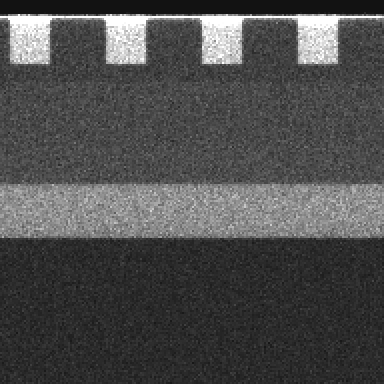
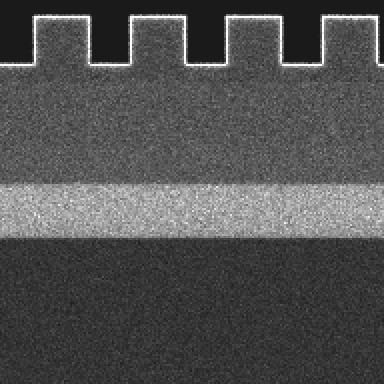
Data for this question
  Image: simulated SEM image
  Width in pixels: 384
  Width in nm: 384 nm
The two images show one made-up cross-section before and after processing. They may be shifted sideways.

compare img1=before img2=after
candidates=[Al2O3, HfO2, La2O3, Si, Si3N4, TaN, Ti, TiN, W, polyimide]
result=removed:HfO2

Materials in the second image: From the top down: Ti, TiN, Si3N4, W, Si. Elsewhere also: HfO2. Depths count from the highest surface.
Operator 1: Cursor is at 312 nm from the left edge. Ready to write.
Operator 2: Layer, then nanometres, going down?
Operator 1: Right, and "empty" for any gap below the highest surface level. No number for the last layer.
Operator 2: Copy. empty 48, Ti 18, TiN 64, Si3N4 38, W 54, Si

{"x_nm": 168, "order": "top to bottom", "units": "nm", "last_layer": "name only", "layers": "Ti 66, TiN 64, Si3N4 38, W 54, Si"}